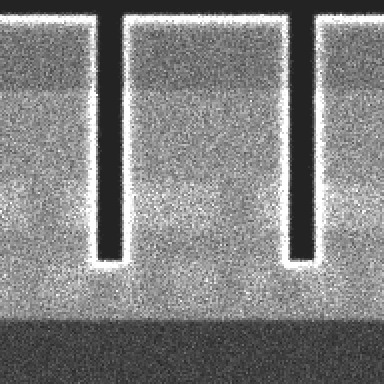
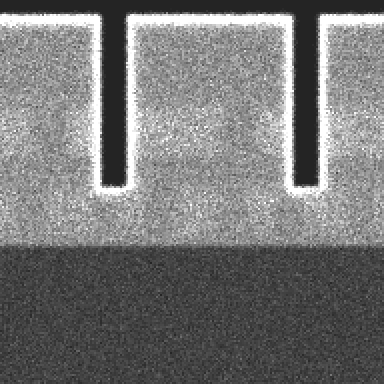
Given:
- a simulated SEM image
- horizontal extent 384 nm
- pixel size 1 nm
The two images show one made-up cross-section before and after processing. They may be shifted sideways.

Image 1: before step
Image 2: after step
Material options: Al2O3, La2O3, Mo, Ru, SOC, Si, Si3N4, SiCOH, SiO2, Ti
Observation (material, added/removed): SOC, removed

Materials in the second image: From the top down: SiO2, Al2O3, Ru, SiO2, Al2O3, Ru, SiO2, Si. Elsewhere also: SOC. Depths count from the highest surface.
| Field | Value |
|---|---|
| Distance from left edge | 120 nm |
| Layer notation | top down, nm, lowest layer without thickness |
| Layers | empty 172, Ru 46, SiO2 12, Si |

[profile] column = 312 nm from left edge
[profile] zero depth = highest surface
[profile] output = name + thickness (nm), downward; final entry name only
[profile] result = empty 172, Ru 46, SiO2 12, Si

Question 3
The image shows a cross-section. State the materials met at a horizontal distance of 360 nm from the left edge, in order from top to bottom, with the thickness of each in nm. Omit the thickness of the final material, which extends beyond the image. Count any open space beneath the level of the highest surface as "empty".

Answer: SiO2 78, Al2O3 14, Ru 48, SiO2 24, Al2O3 8, SiO2 58, Si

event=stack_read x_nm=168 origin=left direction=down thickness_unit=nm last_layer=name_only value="SiO2 78, Al2O3 14, Ru 48, SiO2 24, Al2O3 8, SiO2 58, Si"